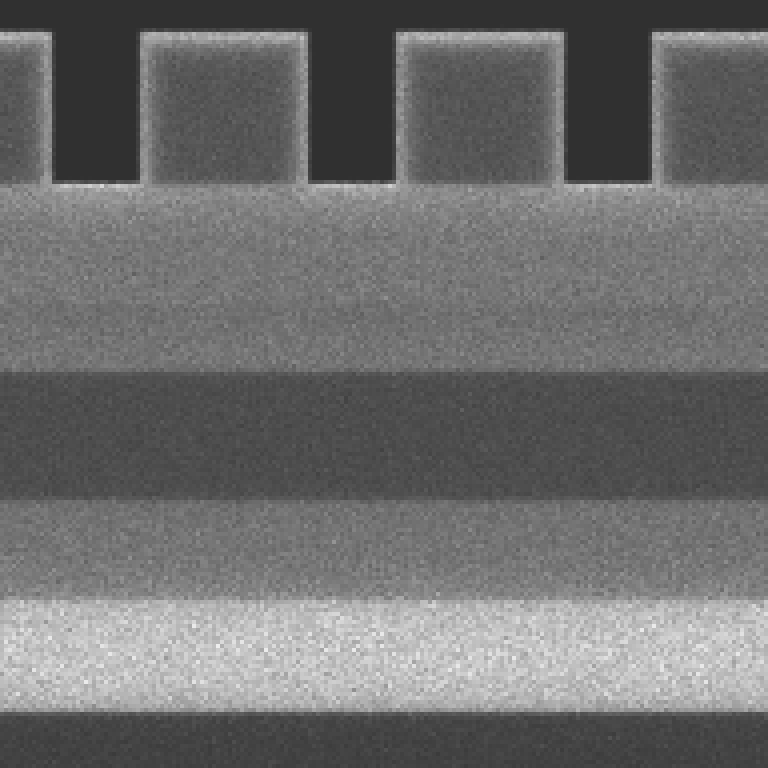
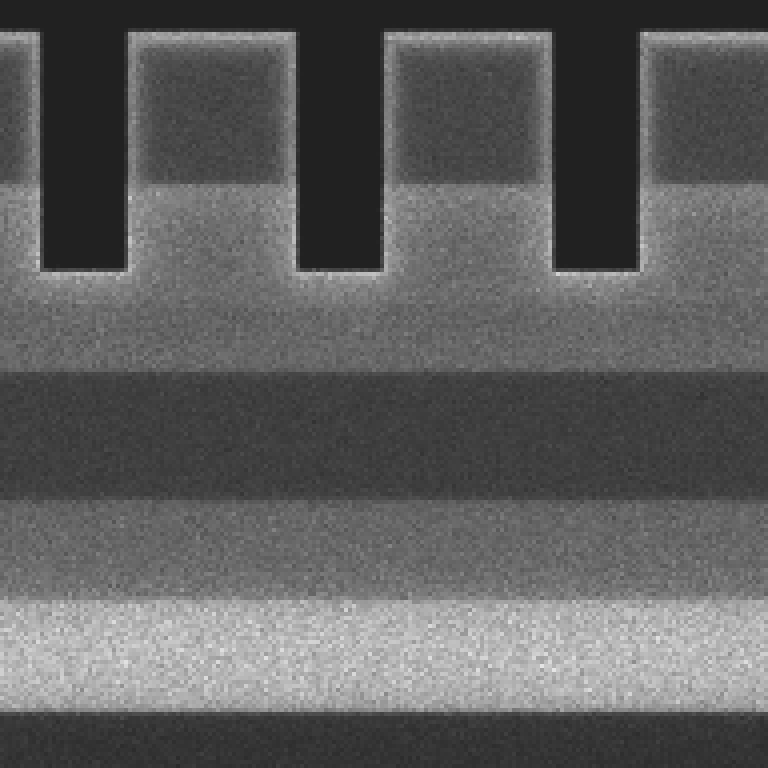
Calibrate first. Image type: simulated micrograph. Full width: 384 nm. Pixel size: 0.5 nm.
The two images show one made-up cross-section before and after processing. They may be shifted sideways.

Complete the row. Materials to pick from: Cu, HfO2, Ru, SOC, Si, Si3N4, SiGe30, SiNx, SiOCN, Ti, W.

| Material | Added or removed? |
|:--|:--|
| W | removed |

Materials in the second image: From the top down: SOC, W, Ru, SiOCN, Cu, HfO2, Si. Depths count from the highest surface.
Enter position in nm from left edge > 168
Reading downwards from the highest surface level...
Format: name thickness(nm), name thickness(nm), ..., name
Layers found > empty 120, W 16, Ru 34, SiOCN 64, Cu 50, HfO2 56, Si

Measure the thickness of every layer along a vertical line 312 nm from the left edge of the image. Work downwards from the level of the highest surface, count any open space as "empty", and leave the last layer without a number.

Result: empty 120, W 16, Ru 34, SiOCN 64, Cu 50, HfO2 56, Si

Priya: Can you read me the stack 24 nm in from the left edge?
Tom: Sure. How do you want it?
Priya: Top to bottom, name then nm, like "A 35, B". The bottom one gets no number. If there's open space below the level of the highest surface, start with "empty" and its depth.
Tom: empty 120, W 16, Ru 34, SiOCN 64, Cu 50, HfO2 56, Si